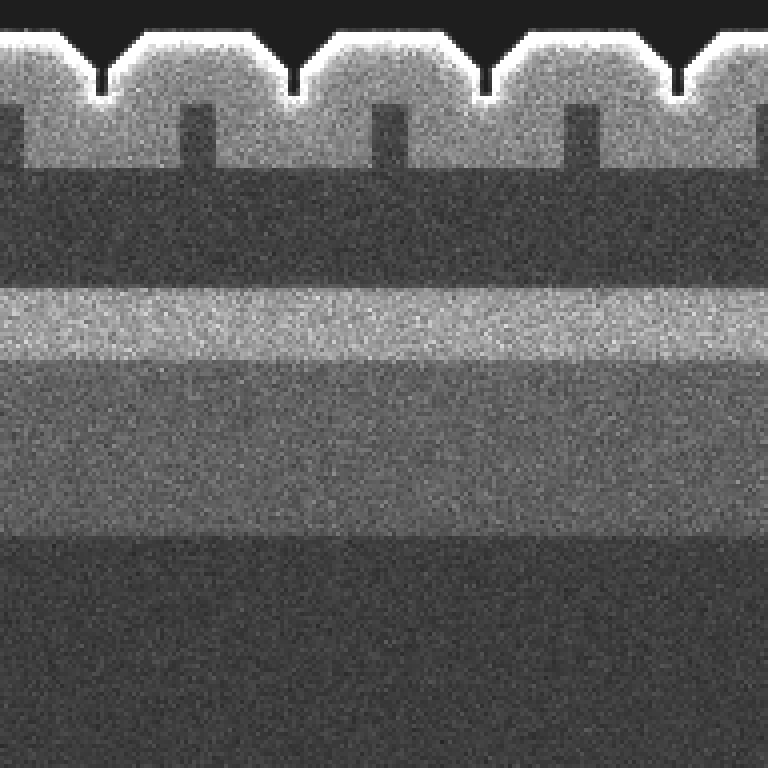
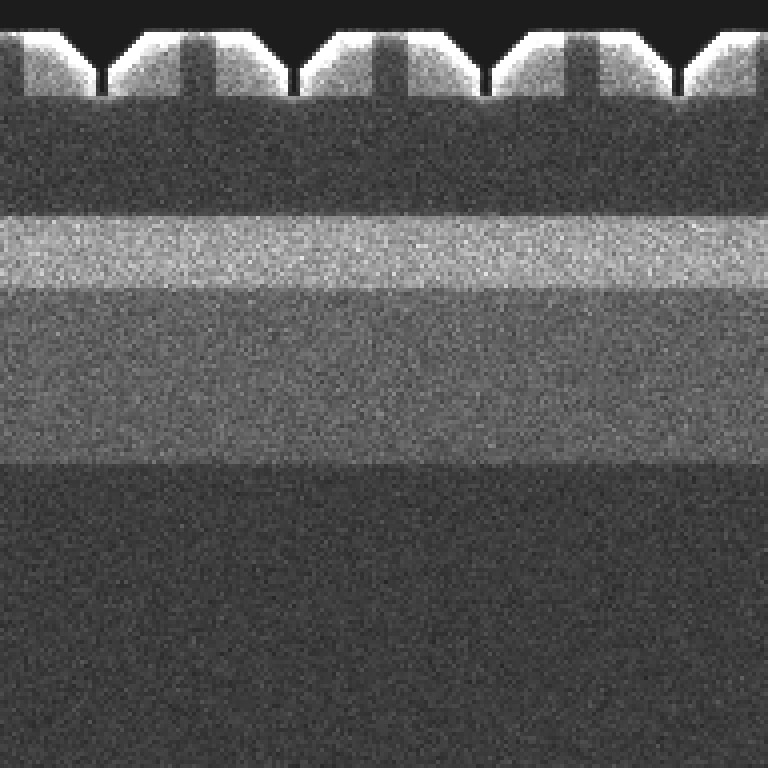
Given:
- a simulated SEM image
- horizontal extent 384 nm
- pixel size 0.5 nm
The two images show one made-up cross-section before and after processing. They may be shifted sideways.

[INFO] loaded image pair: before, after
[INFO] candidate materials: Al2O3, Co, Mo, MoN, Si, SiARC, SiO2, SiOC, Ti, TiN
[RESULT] removed SiO2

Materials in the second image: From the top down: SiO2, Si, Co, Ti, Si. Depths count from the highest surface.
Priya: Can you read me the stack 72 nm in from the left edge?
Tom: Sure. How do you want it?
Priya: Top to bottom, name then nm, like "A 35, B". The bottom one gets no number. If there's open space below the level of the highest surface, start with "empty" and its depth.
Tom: SiO2 32, Si 60, Co 36, Ti 88, Si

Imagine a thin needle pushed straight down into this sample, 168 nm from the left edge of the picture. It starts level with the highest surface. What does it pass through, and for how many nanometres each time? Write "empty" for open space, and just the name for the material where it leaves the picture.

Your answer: SiO2 32, Si 60, Co 36, Ti 88, Si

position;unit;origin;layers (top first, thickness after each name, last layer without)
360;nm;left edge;SiO2 32, Si 60, Co 36, Ti 88, Si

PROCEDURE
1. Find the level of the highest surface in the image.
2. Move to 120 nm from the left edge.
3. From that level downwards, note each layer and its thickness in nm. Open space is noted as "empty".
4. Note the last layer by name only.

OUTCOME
SiO2 32, Si 60, Co 36, Ti 88, Si